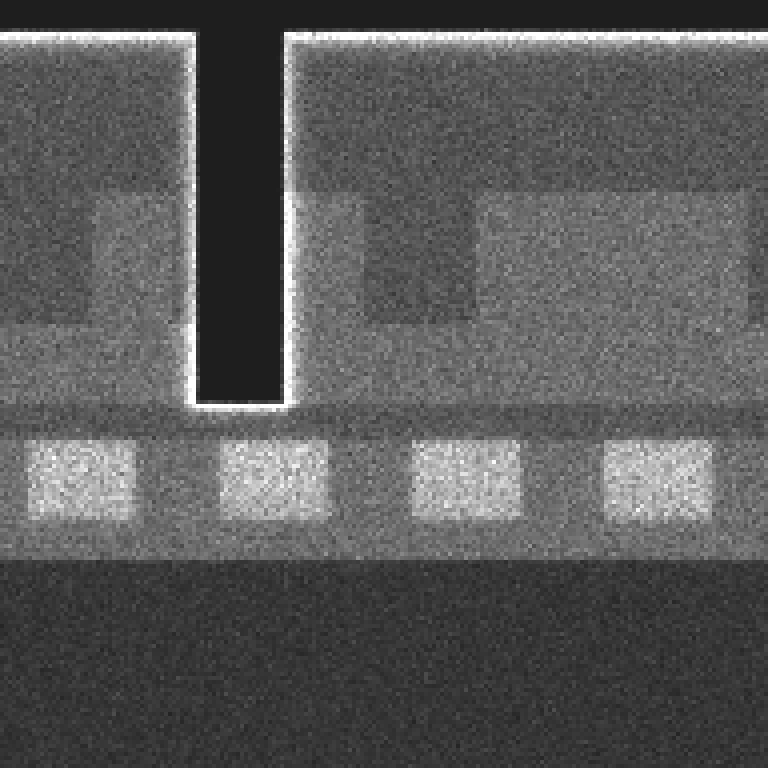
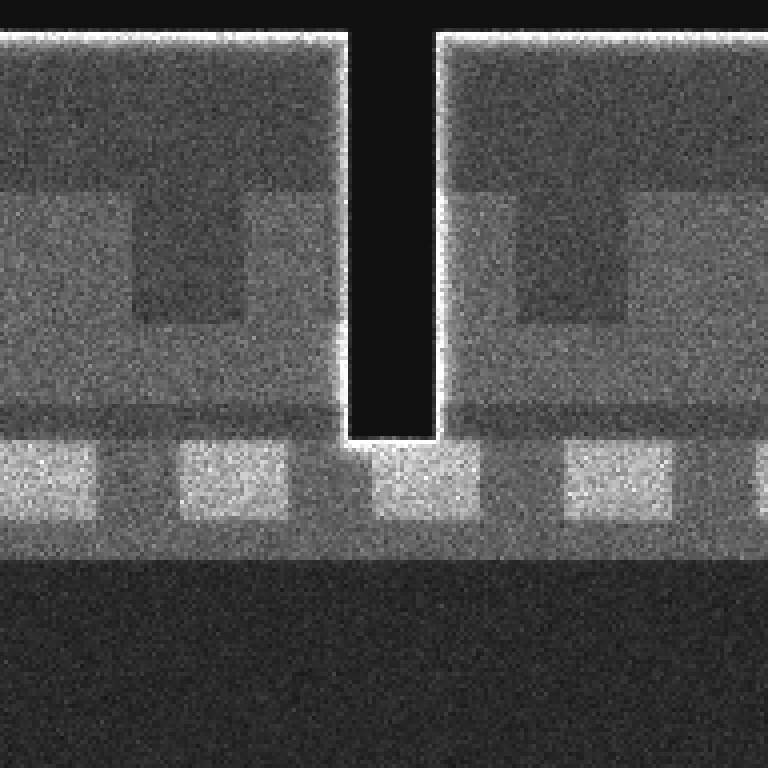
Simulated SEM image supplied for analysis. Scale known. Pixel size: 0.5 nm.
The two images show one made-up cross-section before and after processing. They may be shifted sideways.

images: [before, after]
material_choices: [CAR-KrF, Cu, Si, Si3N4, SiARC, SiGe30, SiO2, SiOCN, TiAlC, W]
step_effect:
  removed: Si3N4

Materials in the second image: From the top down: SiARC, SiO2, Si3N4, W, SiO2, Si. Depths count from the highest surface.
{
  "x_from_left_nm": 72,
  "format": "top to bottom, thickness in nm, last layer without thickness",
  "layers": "SiARC 146, SiO2 40, Si3N4 18, SiO2 60, Si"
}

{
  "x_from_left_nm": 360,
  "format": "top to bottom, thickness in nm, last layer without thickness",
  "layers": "SiARC 80, SiO2 106, Si3N4 18, SiO2 60, Si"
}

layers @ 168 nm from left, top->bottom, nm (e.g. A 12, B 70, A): SiARC 146, SiO2 40, Si3N4 18, SiO2 60, Si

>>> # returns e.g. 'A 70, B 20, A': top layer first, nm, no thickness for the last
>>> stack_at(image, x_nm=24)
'SiARC 80, SiO2 106, Si3N4 18, W 40, SiO2 20, Si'